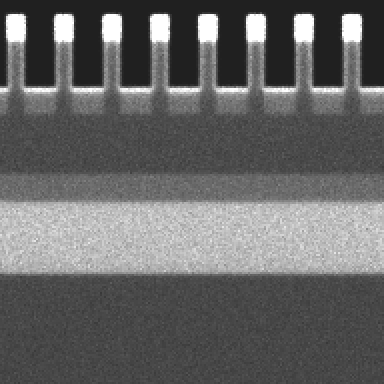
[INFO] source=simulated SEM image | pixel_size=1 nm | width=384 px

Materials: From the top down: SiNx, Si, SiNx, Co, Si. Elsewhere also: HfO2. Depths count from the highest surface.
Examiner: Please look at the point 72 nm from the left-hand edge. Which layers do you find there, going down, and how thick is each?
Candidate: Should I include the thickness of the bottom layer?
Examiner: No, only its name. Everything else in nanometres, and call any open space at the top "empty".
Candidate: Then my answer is empty 72, SiNx 26, Si 60, SiNx 28, Co 72, Si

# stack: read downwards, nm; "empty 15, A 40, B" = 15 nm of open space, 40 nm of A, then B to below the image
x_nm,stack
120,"empty 72, SiNx 26, Si 60, SiNx 28, Co 72, Si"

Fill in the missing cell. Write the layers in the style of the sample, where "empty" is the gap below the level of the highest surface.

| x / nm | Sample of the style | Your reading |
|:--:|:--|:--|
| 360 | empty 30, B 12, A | empty 72, SiNx 26, Si 60, SiNx 28, Co 72, Si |